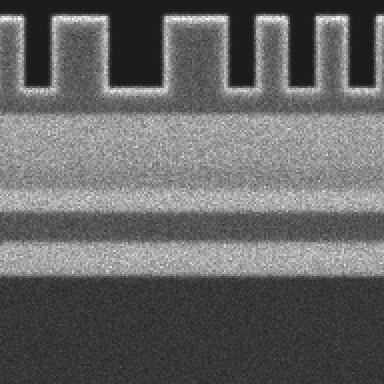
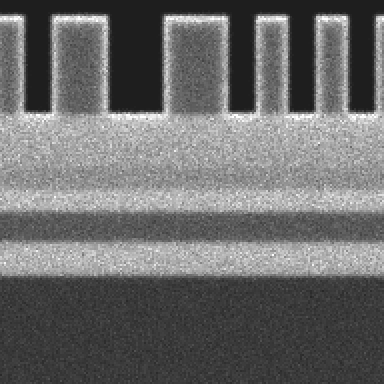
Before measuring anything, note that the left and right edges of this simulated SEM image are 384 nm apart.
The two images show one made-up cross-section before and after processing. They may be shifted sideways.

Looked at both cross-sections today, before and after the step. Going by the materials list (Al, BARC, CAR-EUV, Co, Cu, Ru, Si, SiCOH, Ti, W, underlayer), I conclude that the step removed underlayer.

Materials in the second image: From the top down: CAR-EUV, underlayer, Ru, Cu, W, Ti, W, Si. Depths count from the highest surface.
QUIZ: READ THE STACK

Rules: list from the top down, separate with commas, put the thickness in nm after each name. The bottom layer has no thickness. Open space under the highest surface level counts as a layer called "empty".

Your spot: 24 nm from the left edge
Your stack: empty 98, Ru 54, Cu 22, W 22, Ti 30, W 34, Si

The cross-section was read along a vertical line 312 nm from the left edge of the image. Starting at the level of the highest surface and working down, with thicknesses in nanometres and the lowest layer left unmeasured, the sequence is empty 98, Ru 54, Cu 22, W 22, Ti 30, W 34, Si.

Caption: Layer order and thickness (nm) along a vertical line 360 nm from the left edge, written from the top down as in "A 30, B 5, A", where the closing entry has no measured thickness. empty 98, Ru 54, Cu 22, W 22, Ti 30, W 34, Si